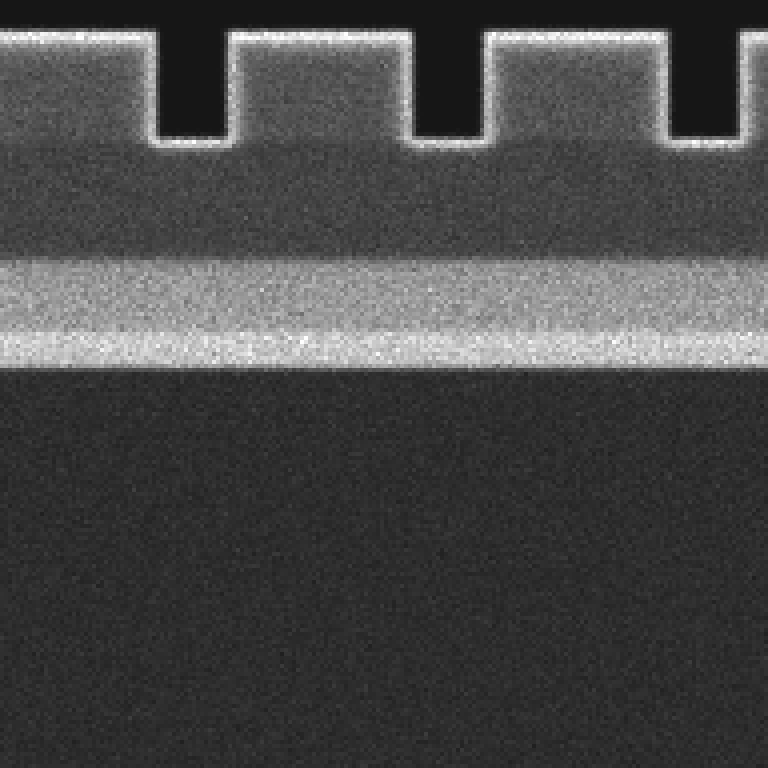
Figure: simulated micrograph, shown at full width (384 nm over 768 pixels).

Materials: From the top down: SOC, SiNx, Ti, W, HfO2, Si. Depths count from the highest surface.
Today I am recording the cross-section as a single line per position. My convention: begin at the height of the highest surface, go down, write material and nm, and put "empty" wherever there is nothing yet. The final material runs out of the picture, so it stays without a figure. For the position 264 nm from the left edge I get SOC 54, SiNx 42, Ti 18, W 36, HfO2 18, Si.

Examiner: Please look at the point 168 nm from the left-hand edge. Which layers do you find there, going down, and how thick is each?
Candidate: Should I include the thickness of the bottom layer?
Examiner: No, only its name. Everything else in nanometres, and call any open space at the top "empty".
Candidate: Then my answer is SOC 54, SiNx 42, Ti 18, W 36, HfO2 18, Si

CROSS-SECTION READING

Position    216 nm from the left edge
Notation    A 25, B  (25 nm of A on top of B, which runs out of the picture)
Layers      empty 54, SiNx 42, Ti 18, W 36, HfO2 18, Si